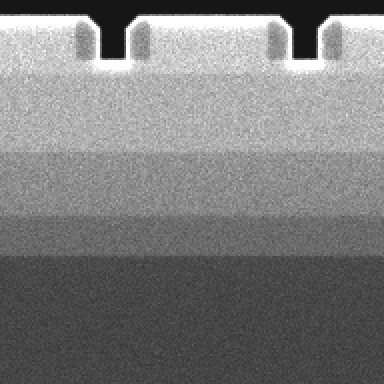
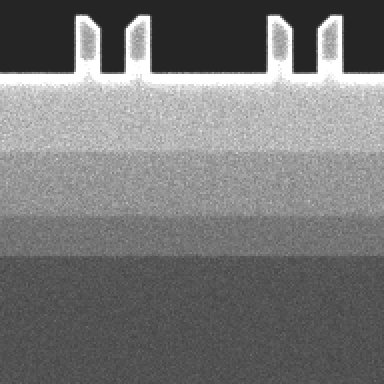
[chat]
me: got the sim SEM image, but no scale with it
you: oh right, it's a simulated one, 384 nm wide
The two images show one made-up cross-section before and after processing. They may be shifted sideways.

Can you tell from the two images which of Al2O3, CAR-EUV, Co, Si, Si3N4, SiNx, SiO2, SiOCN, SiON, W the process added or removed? Yes, it removed Al2O3.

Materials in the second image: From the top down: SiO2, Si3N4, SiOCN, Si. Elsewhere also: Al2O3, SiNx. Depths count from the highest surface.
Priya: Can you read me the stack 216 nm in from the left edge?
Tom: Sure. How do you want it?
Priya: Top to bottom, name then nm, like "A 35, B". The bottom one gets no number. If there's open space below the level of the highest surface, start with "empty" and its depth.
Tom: empty 58, SiO2 78, Si3N4 64, SiOCN 40, Si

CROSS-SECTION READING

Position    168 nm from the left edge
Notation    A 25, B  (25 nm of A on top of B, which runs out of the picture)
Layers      empty 58, SiO2 78, Si3N4 64, SiOCN 40, Si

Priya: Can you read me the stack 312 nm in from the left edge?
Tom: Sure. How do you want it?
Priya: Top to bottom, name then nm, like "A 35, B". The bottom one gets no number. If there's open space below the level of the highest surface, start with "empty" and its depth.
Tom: empty 58, SiO2 78, Si3N4 64, SiOCN 40, Si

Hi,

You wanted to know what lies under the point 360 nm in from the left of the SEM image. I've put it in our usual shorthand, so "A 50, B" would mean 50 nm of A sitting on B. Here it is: empty 58, SiO2 78, Si3N4 64, SiOCN 40, Si